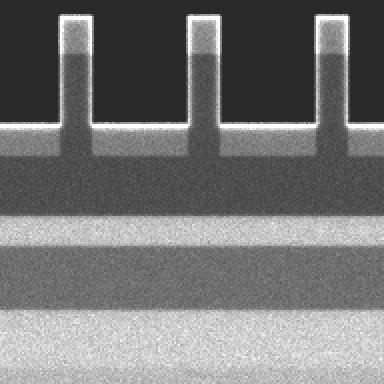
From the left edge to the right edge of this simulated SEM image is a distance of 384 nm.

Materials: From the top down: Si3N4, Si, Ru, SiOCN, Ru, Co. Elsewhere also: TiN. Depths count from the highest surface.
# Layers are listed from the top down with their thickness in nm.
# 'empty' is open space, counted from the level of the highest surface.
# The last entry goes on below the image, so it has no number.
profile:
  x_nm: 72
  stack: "TiN 38, Si 162, Ru 30, SiOCN 64, Ru 58, Co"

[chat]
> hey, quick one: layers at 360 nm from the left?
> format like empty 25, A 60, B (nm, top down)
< empty 108, Si3N4 32, Si 60, Ru 30, SiOCN 64, Ru 58, Co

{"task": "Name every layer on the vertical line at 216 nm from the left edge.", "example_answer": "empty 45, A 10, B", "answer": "TiN 38, Si 162, Ru 30, SiOCN 64, Ru 58, Co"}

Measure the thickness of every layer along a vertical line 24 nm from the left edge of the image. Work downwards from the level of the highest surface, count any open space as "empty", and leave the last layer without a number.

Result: empty 108, Si3N4 32, Si 60, Ru 30, SiOCN 64, Ru 58, Co